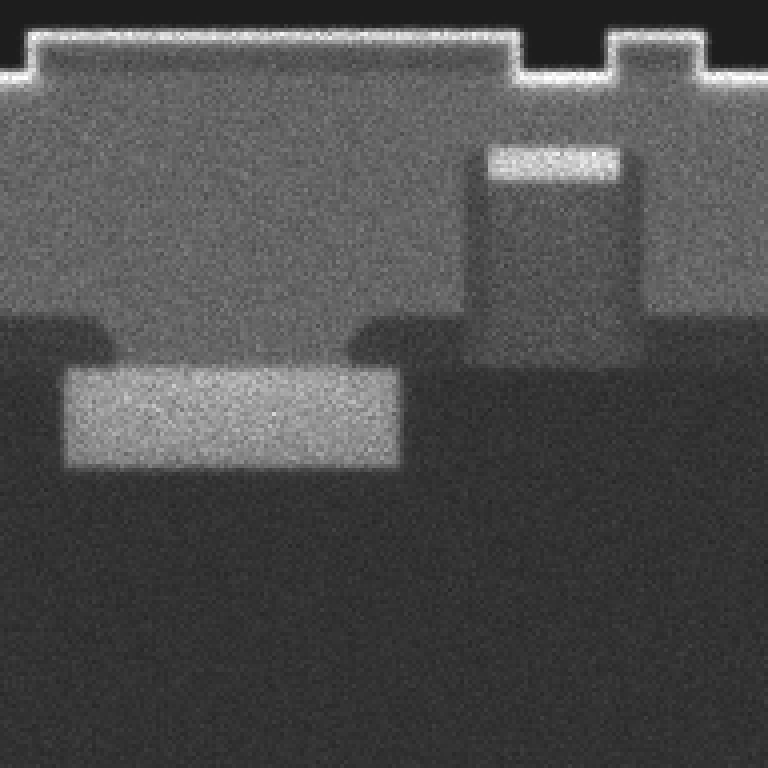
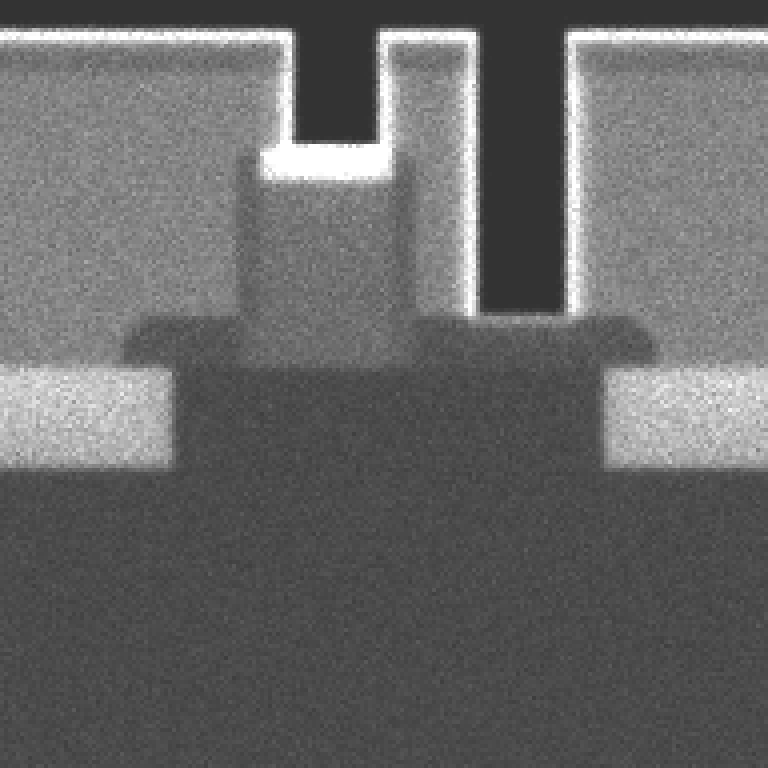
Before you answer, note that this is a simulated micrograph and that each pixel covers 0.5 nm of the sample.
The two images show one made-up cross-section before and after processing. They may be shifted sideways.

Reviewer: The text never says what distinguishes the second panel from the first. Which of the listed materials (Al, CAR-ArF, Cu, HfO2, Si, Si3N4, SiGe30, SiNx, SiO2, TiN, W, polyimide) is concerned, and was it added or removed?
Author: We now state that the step removed SiO2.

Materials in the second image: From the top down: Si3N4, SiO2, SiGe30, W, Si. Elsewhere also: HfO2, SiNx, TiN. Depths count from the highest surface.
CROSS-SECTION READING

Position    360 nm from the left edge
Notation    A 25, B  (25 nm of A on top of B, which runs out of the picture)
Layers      Si3N4 20, SiO2 148, W 50, Si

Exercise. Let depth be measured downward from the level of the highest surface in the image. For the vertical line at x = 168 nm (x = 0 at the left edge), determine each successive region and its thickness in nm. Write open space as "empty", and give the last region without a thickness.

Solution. empty 58, HfO2 16, TiN 94, Si